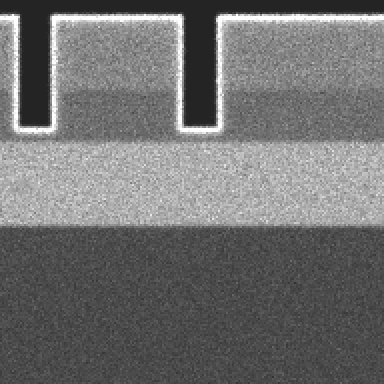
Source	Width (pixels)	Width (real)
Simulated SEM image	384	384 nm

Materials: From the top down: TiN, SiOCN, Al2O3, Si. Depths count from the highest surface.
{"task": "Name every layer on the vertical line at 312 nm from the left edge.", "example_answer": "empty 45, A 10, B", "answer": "TiN 74, SiOCN 52, Al2O3 84, Si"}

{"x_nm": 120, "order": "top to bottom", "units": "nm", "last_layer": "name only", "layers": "TiN 74, SiOCN 52, Al2O3 84, Si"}